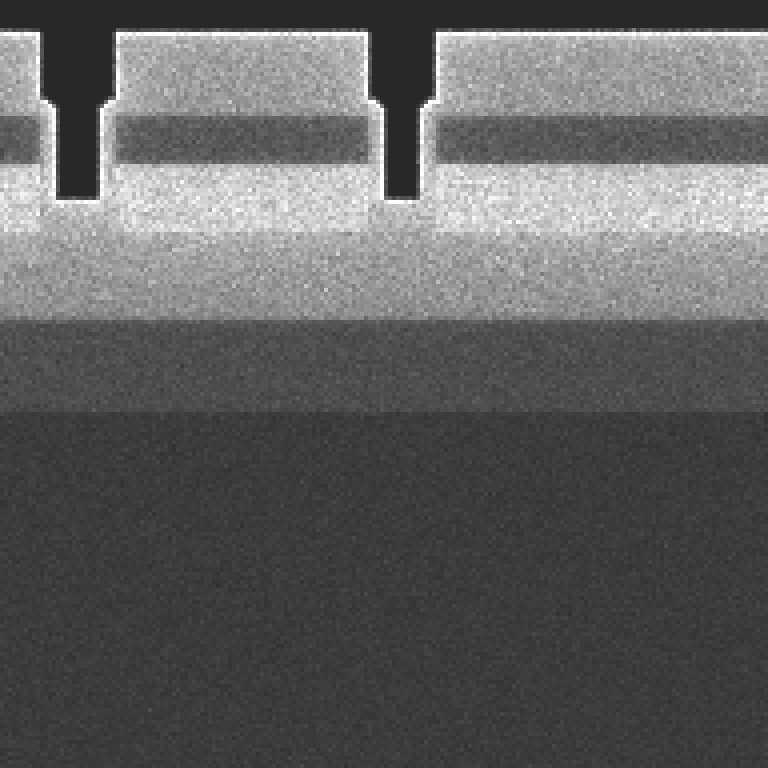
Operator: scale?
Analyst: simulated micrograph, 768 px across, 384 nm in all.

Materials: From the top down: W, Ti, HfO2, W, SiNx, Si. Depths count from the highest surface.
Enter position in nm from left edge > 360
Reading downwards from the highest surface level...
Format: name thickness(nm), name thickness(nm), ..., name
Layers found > W 42, Ti 24, HfO2 34, W 44, SiNx 46, Si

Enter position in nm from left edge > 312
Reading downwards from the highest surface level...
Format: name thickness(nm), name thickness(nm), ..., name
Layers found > W 42, Ti 24, HfO2 34, W 44, SiNx 46, Si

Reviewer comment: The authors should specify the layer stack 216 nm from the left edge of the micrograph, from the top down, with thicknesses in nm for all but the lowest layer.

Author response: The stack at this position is empty 34, W 110, SiNx 46, Si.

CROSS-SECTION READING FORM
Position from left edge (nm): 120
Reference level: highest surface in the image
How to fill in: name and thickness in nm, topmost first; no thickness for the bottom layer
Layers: W 42, Ti 24, HfO2 34, W 44, SiNx 46, Si